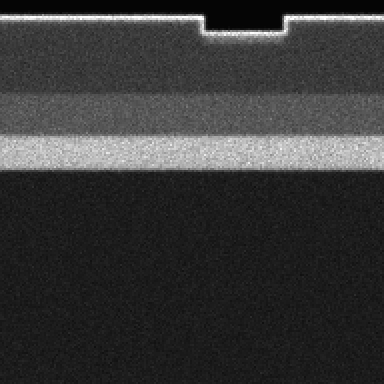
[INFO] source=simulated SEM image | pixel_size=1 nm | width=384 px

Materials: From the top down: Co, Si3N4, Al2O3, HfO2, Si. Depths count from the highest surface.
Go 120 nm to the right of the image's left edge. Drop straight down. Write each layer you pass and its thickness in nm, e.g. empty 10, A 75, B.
Si3N4 78, Al2O3 42, HfO2 34, Si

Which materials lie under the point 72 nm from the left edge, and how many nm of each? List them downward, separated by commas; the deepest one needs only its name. Si3N4 78, Al2O3 42, HfO2 34, Si